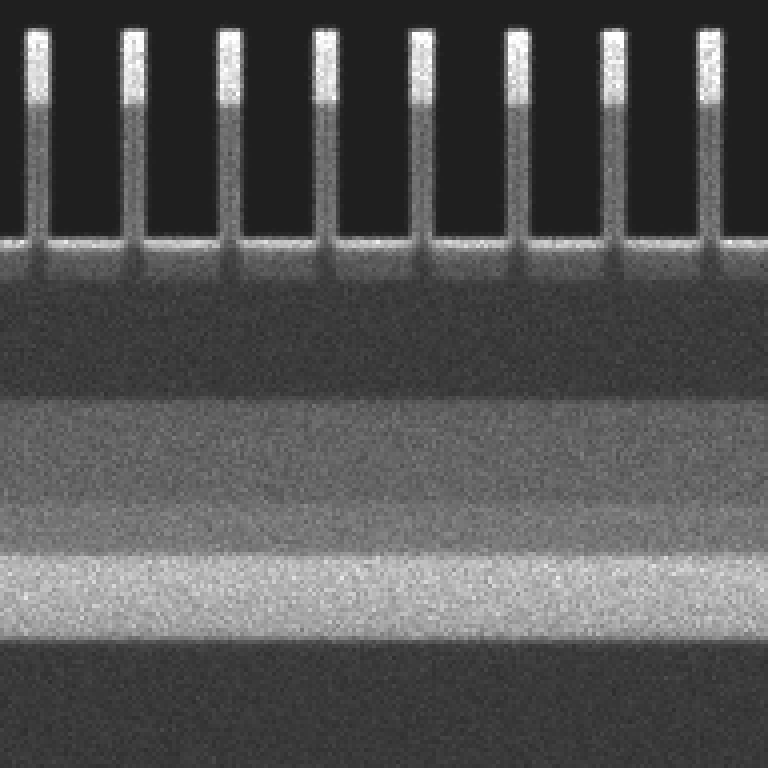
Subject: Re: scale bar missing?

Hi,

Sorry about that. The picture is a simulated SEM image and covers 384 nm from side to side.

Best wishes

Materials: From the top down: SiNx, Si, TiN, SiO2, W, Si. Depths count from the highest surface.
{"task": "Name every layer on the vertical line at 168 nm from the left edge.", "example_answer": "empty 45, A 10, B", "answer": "empty 104, SiNx 20, Si 60, TiN 52, SiO2 26, W 42, Si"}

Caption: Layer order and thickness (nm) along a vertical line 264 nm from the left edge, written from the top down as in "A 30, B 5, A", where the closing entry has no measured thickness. empty 104, SiNx 20, Si 60, TiN 52, SiO2 26, W 42, Si